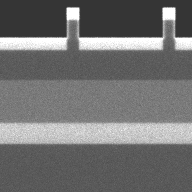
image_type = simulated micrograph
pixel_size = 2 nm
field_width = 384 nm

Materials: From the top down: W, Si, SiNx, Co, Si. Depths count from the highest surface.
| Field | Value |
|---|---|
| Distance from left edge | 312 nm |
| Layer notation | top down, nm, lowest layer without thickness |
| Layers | empty 60, W 24, Si 60, SiNx 86, Co 42, Si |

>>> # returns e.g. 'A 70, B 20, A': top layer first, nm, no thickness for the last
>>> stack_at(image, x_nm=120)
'empty 60, W 24, Si 60, SiNx 86, Co 42, Si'